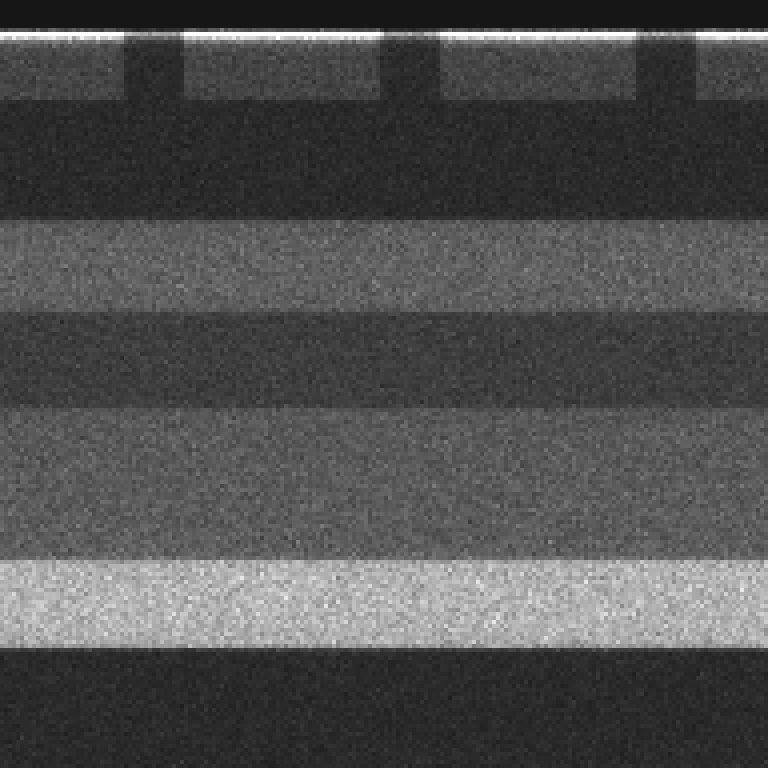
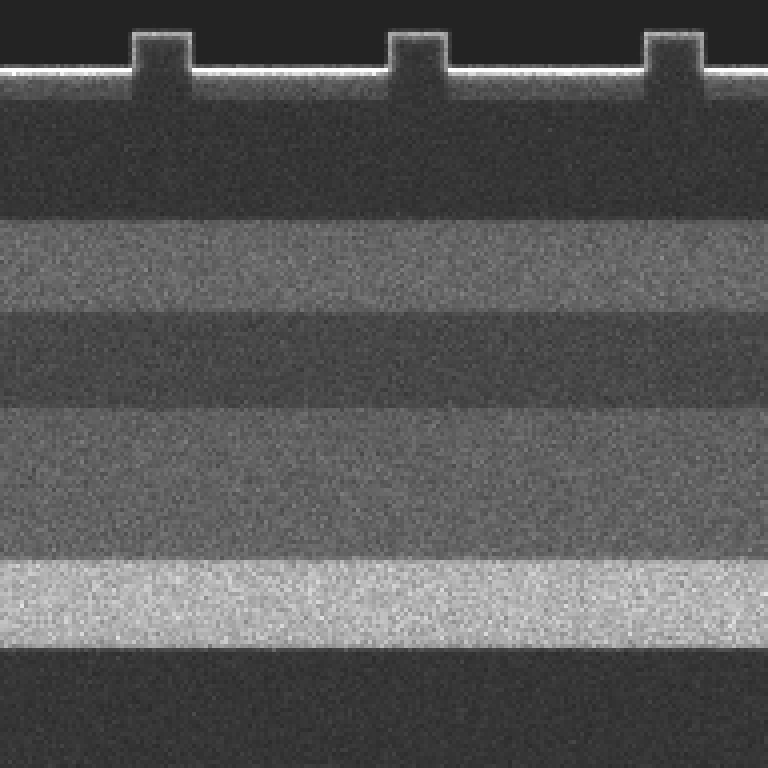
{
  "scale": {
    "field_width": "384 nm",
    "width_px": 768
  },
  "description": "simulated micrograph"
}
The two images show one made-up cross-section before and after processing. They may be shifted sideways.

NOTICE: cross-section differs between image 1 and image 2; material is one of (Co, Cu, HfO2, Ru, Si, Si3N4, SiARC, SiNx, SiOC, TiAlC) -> removed: Si3N4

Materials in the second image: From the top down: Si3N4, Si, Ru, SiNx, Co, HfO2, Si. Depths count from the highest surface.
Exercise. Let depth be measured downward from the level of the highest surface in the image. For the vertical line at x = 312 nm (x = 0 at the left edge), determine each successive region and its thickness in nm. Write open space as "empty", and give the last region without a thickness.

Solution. empty 18, Si3N4 16, Si 60, Ru 46, SiNx 48, Co 76, HfO2 44, Si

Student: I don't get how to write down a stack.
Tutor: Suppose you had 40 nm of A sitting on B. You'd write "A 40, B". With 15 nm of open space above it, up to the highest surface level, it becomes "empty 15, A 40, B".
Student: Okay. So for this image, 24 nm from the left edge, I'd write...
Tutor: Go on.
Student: empty 18, Si3N4 16, Si 60, Ru 46, SiNx 48, Co 76, HfO2 44, Si